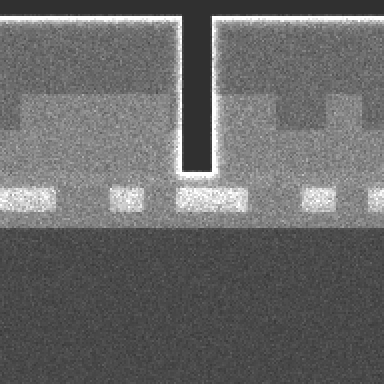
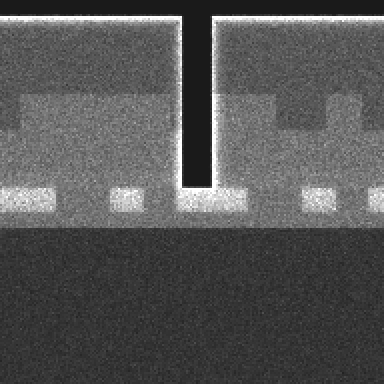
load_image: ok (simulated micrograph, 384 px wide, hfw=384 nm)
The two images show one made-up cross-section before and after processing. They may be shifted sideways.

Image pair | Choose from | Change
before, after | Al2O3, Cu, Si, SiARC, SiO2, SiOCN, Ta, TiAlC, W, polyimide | Al2O3 (removed)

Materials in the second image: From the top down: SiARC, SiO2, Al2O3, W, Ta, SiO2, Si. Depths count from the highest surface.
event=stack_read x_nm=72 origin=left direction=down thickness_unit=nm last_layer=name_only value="SiARC 78, SiO2 78, Al2O3 16, SiO2 40, Si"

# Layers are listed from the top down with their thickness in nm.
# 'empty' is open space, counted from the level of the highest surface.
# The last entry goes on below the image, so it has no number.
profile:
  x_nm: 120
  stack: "SiARC 78, SiO2 78, Al2O3 16, W 18, Ta 6, SiO2 16, Si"